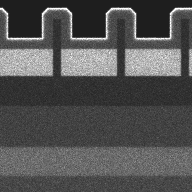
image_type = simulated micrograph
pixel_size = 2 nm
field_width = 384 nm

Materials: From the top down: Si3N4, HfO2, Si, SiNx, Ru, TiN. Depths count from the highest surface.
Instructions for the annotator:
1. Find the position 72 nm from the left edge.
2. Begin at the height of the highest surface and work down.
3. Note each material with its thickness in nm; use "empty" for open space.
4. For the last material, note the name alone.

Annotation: empty 60, Si3N4 22, HfO2 54, Si 60, SiNx 82, Ru 58, TiN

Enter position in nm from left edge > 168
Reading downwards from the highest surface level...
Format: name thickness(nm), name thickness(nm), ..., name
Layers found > empty 60, Si3N4 22, HfO2 54, Si 60, SiNx 82, Ru 58, TiN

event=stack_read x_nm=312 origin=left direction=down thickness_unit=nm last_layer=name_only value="empty 60, Si3N4 22, HfO2 54, Si 60, SiNx 82, Ru 58, TiN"